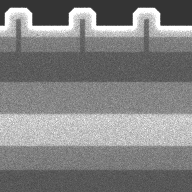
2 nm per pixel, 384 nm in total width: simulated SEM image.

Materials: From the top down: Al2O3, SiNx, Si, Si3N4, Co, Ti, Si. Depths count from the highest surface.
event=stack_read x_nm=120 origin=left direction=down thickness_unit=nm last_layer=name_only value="empty 36, Al2O3 22, SiNx 30, Si 60, Si3N4 64, Co 64, Ti 48, Si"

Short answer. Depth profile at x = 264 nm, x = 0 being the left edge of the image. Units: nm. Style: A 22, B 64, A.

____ empty 36, Al2O3 22, SiNx 30, Si 60, Si3N4 64, Co 64, Ti 48, Si